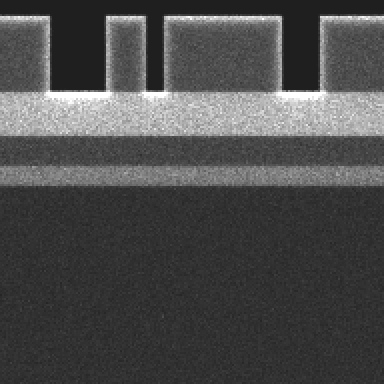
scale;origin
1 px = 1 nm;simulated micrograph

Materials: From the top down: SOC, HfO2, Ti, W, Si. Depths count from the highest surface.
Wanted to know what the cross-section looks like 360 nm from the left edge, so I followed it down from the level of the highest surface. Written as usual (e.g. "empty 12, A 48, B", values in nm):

SOC 76, HfO2 44, Ti 30, W 20, Si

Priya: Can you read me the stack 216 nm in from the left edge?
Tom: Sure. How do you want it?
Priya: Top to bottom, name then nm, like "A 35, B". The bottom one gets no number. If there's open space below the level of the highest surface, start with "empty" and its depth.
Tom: SOC 76, HfO2 44, Ti 30, W 20, Si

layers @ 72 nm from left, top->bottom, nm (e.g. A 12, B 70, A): empty 76, HfO2 44, Ti 30, W 20, Si